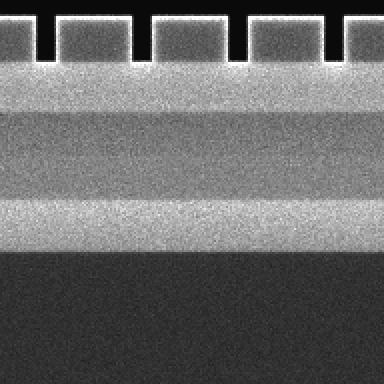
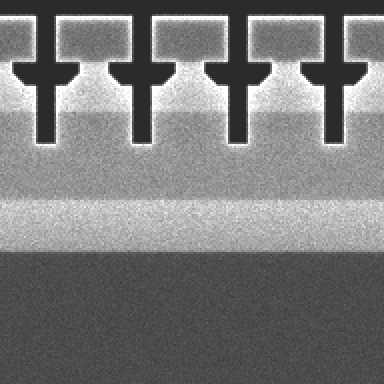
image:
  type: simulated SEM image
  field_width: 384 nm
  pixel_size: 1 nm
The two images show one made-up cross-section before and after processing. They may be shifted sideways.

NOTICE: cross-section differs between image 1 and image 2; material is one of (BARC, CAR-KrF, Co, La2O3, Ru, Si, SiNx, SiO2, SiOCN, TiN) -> removed: Ru and TiN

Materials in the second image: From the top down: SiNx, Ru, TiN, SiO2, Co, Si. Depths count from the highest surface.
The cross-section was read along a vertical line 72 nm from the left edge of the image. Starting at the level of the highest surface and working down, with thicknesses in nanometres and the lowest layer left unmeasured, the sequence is SiNx 46, empty 18, Ru 32, TiN 44, SiO2 44, Co 52, Si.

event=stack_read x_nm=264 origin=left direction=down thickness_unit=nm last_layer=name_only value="SiNx 46, empty 18, Ru 32, TiN 44, SiO2 44, Co 52, Si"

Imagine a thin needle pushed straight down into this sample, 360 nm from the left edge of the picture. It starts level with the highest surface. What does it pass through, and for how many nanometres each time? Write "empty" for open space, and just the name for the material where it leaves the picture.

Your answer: SiNx 46, empty 18, Ru 32, TiN 44, SiO2 44, Co 52, Si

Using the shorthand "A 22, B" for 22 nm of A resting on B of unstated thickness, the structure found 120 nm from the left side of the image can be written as SiNx 46, empty 24, Ru 26, TiN 44, SiO2 44, Co 52, Si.